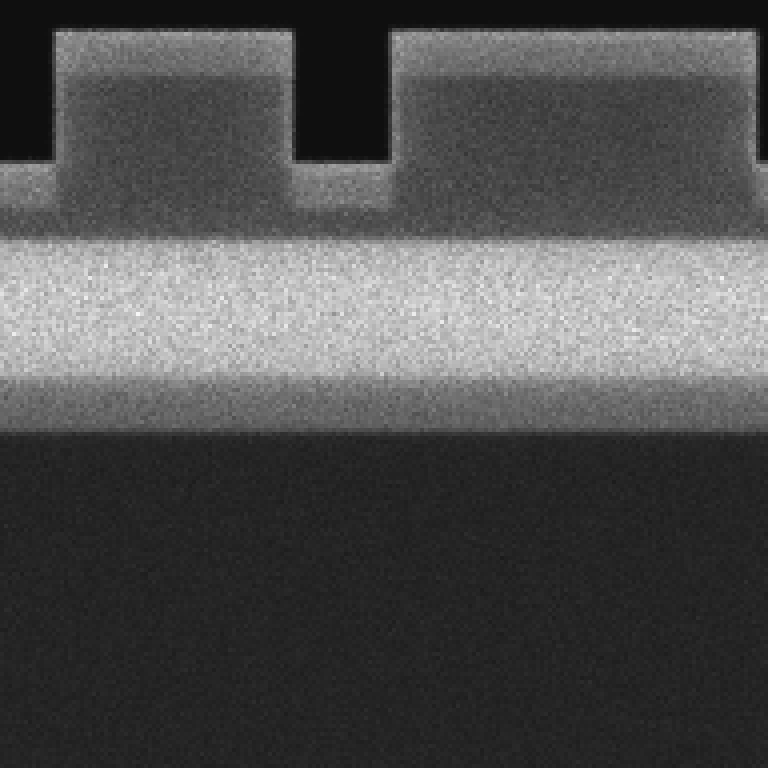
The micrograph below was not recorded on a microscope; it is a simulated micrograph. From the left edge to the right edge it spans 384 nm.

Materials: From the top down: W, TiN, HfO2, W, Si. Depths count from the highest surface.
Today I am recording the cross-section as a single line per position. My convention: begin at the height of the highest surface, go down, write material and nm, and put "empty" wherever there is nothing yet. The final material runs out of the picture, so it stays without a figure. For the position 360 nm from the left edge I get W 22, TiN 82, HfO2 68, W 28, Si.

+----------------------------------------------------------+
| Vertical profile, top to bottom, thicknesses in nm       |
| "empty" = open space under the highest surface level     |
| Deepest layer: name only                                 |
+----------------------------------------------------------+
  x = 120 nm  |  W 22, TiN 82, HfO2 68, W 28, Si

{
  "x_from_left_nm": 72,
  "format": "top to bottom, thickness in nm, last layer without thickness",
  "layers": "W 22, TiN 82, HfO2 68, W 28, Si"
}